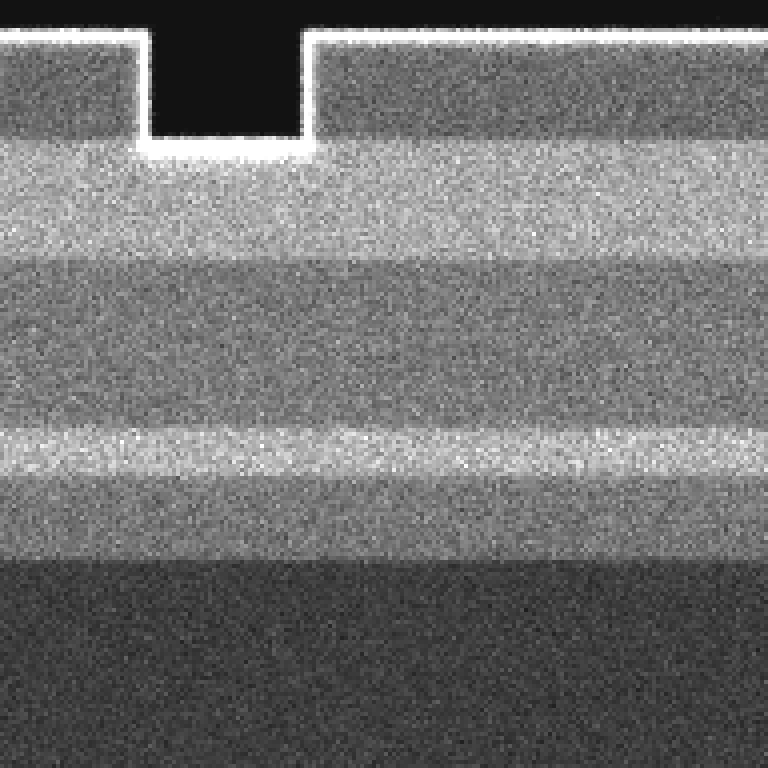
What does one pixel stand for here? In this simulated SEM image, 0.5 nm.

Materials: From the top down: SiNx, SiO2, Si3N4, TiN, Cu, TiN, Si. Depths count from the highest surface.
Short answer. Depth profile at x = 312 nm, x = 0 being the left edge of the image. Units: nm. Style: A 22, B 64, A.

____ SiNx 54, SiO2 60, Si3N4 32, TiN 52, Cu 24, TiN 42, Si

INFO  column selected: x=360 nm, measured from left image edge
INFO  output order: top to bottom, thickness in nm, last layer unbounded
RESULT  SiNx 54, SiO2 60, Si3N4 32, TiN 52, Cu 24, TiN 42, Si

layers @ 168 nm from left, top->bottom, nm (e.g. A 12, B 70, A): SiNx 54, SiO2 60, Si3N4 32, TiN 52, Cu 24, TiN 42, Si